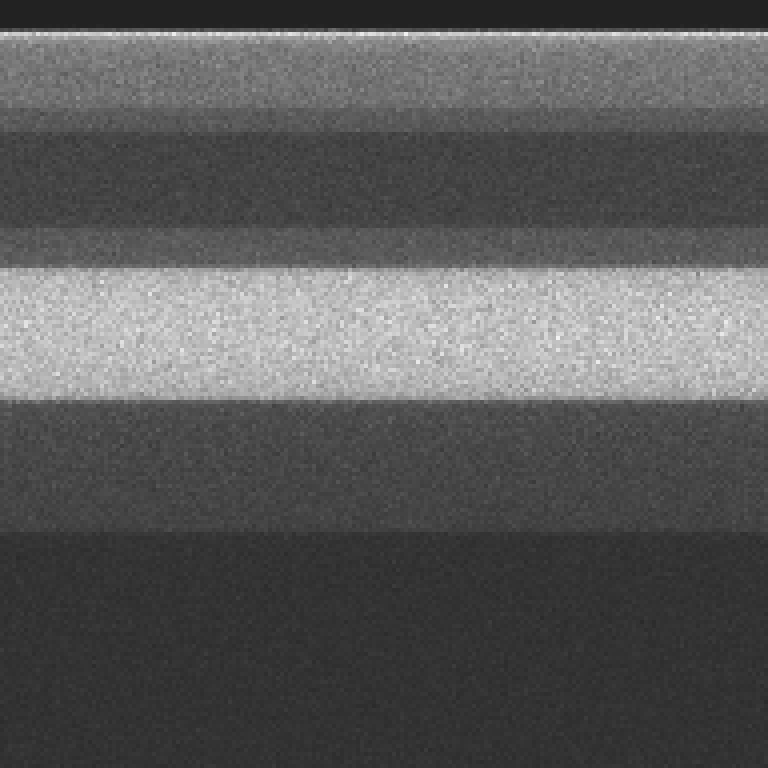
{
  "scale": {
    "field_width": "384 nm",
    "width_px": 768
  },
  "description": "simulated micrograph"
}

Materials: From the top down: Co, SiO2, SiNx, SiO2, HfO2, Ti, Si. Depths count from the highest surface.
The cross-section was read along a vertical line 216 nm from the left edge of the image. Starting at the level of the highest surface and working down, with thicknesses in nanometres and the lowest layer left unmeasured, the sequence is Co 38, SiO2 12, SiNx 48, SiO2 20, HfO2 66, Ti 66, Si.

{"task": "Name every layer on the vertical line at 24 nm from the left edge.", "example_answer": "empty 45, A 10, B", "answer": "Co 38, SiO2 12, SiNx 48, SiO2 20, HfO2 66, Ti 66, Si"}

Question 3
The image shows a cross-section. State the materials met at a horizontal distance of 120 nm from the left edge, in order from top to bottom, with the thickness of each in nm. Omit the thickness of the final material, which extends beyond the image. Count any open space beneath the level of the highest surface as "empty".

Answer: Co 38, SiO2 12, SiNx 48, SiO2 20, HfO2 66, Ti 66, Si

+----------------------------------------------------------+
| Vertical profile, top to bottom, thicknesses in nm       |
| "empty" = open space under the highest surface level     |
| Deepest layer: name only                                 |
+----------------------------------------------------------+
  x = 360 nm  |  Co 38, SiO2 12, SiNx 48, SiO2 20, HfO2 66, Ti 66, Si